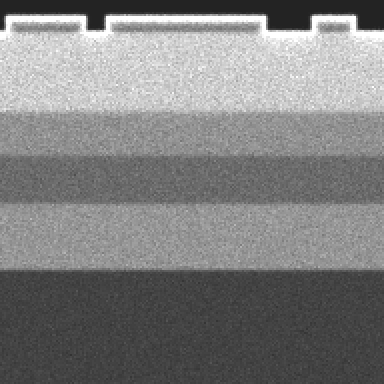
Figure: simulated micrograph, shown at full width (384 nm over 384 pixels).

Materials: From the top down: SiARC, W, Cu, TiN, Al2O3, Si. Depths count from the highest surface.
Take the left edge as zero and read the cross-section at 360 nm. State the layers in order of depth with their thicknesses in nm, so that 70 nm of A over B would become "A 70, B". empty 16, W 80, Cu 44, TiN 48, Al2O3 66, Si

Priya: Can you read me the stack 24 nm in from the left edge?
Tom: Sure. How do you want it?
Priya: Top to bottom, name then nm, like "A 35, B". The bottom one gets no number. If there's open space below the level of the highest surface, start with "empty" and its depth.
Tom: SiARC 16, W 80, Cu 44, TiN 48, Al2O3 66, Si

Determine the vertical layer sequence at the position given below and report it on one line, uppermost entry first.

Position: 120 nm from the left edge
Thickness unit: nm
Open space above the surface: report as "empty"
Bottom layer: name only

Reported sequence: SiARC 16, W 80, Cu 44, TiN 48, Al2O3 66, Si